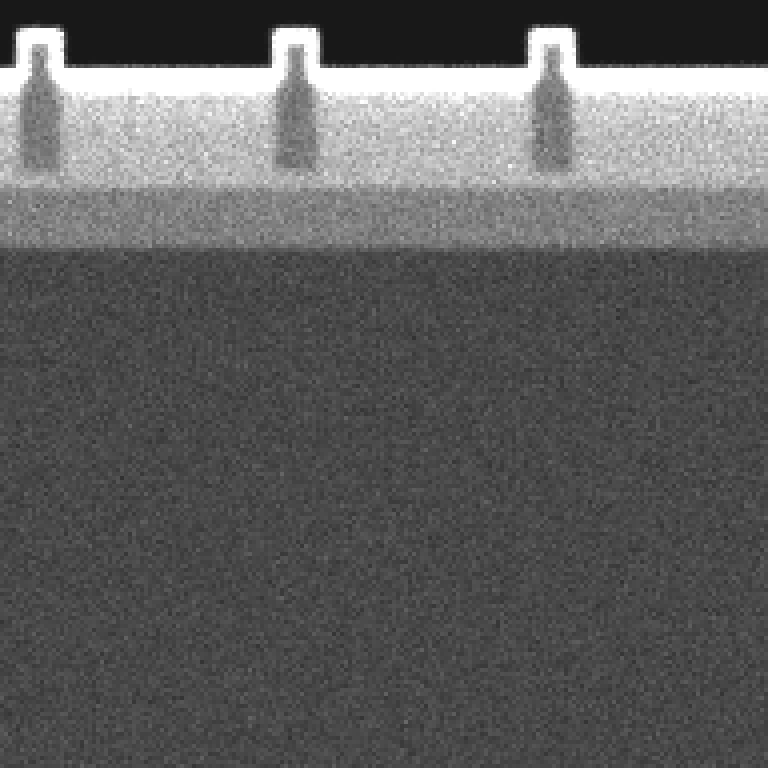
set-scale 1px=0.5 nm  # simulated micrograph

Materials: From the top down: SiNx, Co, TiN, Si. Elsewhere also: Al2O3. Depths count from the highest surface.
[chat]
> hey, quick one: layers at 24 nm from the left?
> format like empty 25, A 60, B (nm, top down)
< SiNx 70, Co 8, TiN 30, Si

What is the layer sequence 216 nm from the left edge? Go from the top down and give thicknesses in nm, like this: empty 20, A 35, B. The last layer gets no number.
empty 20, Al2O3 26, Co 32, TiN 30, Si